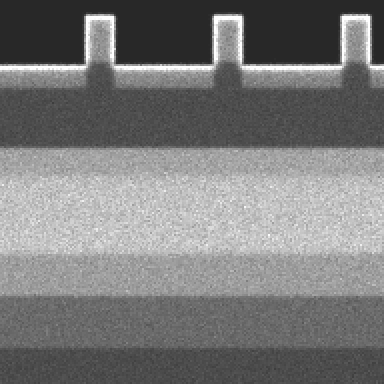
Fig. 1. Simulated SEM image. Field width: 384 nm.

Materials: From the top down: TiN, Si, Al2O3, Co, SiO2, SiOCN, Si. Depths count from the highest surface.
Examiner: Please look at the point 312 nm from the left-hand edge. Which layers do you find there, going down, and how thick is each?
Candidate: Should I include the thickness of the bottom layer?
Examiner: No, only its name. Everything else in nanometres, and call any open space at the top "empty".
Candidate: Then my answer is empty 50, TiN 22, Si 60, Al2O3 28, Co 78, SiO2 42, SiOCN 52, Si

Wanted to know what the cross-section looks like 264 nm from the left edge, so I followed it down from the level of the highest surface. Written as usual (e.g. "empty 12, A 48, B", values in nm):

empty 50, TiN 22, Si 60, Al2O3 28, Co 78, SiO2 42, SiOCN 52, Si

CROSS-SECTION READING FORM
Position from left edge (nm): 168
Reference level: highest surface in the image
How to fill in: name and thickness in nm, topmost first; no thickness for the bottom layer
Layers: empty 50, TiN 22, Si 60, Al2O3 28, Co 78, SiO2 42, SiOCN 52, Si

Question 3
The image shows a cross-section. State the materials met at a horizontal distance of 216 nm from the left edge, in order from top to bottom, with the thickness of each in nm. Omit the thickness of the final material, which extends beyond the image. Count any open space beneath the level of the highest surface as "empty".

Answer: TiN 46, Si 86, Al2O3 28, Co 78, SiO2 42, SiOCN 52, Si